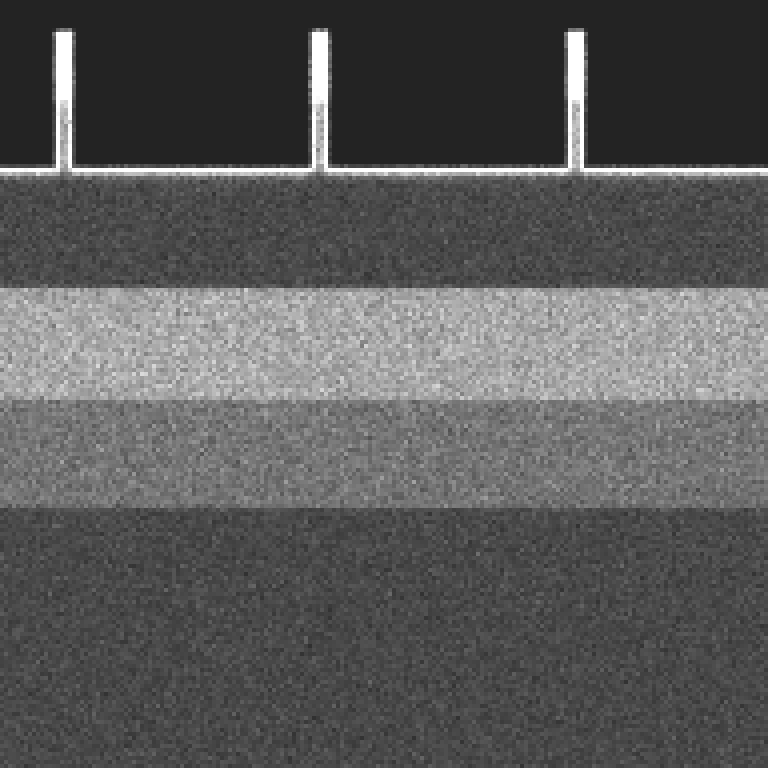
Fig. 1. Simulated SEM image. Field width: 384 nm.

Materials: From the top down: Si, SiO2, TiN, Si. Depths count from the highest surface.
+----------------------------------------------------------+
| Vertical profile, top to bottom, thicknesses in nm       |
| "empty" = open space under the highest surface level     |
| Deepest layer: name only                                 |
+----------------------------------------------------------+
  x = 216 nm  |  empty 68, Si 60, SiO2 56, TiN 54, Si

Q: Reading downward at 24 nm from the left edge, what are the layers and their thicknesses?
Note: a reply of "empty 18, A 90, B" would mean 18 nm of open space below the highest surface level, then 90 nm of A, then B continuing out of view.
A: empty 68, Si 60, SiO2 56, TiN 54, Si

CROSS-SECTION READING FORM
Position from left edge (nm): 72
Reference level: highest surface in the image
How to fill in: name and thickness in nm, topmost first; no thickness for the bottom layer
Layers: empty 68, Si 60, SiO2 56, TiN 54, Si